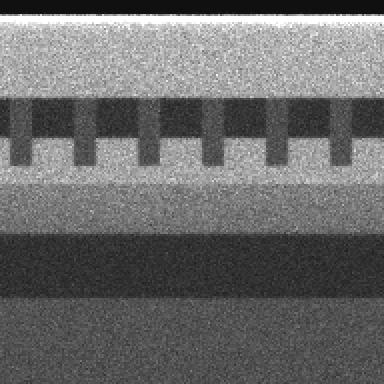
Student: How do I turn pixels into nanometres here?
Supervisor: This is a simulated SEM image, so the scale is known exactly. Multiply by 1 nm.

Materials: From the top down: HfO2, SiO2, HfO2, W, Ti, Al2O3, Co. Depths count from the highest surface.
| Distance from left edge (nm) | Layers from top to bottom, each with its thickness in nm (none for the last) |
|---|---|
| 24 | HfO2 82, SiO2 68, HfO2 18, W 50, Ti 64, Al2O3 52, Co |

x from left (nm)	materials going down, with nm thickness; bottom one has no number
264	HfO2 82, Ti 40, HfO2 46, W 50, Ti 64, Al2O3 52, Co